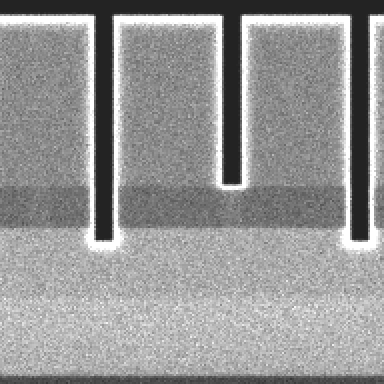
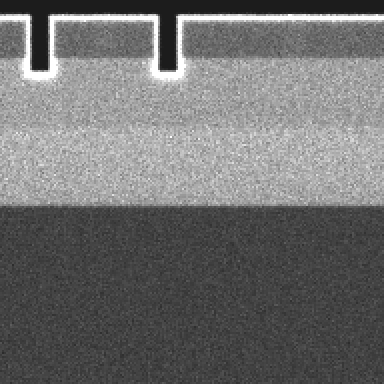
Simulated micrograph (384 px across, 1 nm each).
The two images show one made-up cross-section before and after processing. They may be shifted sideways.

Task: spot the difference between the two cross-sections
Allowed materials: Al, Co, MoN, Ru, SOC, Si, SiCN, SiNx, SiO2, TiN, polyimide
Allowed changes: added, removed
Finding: removed SOC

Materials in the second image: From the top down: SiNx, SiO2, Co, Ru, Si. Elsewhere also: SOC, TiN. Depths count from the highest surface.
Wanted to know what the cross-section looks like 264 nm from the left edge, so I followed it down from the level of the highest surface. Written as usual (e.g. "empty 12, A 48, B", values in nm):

SiNx 42, SiO2 42, Co 28, Ru 78, Si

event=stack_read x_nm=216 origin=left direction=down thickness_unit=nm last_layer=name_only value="SiNx 42, SiO2 42, Co 28, Ru 78, Si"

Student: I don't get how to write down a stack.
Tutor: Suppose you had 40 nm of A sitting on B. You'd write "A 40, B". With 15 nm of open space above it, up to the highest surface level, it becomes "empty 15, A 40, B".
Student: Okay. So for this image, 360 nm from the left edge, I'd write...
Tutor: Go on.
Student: SiNx 42, SiO2 42, Co 28, Ru 78, Si